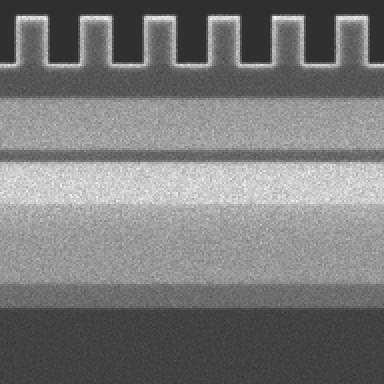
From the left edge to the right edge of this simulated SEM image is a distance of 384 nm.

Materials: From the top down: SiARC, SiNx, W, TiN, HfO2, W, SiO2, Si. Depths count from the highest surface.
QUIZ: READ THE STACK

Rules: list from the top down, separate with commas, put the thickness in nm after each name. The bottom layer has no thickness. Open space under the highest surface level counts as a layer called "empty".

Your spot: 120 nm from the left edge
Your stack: empty 48, SiNx 34, W 52, TiN 12, HfO2 42, W 80, SiO2 24, Si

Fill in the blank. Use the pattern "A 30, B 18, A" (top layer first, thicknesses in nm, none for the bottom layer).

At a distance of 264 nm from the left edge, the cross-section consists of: empty 48, SiNx 34, W 52, TiN 12, HfO2 42, W 80, SiO2 24, Si